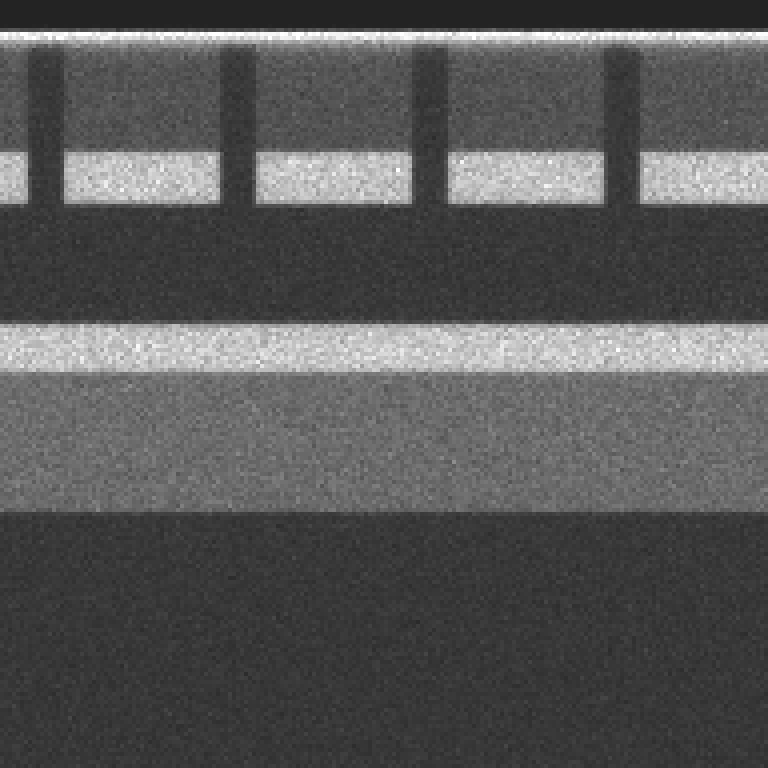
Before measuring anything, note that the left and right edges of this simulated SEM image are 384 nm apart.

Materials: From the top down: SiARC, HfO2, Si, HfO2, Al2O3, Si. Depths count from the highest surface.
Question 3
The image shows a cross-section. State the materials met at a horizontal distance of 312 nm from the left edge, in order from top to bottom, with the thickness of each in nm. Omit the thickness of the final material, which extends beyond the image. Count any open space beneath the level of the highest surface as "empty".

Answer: SiARC 6, Si 140, HfO2 24, Al2O3 70, Si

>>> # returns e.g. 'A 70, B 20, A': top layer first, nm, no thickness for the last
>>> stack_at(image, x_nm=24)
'SiARC 6, Si 140, HfO2 24, Al2O3 70, Si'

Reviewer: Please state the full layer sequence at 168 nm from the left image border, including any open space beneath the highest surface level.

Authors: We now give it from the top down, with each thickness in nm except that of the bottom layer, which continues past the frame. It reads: SiARC 60, HfO2 26, Si 60, HfO2 24, Al2O3 70, Si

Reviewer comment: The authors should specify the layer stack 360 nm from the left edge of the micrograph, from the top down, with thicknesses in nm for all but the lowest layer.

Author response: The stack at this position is SiARC 60, HfO2 26, Si 60, HfO2 24, Al2O3 70, Si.